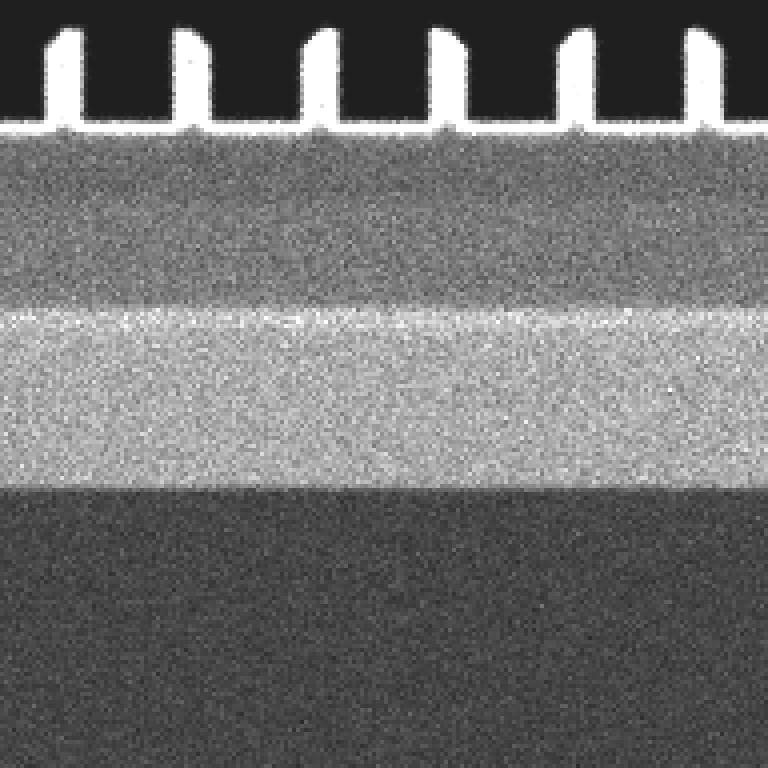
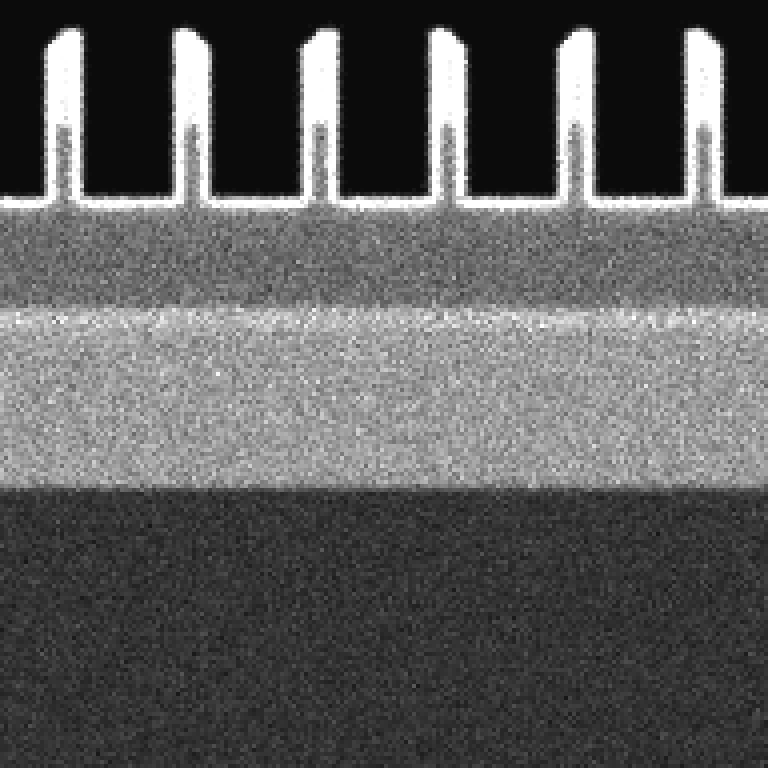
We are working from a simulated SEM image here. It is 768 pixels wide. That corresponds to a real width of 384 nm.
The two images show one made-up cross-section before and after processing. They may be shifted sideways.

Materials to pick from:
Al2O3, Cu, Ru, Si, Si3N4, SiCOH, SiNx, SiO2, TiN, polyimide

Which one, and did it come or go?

SiNx - removed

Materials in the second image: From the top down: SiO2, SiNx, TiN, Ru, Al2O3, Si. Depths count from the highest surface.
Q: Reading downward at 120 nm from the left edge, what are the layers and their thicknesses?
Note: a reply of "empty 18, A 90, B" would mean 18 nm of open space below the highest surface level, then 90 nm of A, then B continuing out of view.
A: empty 84, TiN 54, Ru 10, Al2O3 80, Si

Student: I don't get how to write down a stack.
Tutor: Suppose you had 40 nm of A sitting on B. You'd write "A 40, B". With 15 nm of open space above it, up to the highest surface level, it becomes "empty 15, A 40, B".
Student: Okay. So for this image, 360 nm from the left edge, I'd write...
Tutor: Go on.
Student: empty 84, TiN 54, Ru 10, Al2O3 80, Si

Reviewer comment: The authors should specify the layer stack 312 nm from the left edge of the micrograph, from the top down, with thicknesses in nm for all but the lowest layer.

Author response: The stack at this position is empty 84, TiN 54, Ru 10, Al2O3 80, Si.